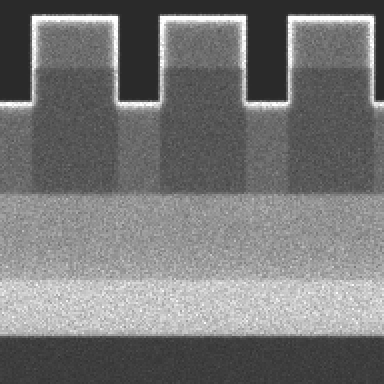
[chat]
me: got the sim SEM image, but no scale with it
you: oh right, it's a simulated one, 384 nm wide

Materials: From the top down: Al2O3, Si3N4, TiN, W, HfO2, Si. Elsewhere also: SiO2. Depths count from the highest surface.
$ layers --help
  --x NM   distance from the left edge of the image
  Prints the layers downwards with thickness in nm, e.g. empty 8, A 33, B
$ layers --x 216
Al2O3 52, Si3N4 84, TiN 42, W 86, HfO2 56, Si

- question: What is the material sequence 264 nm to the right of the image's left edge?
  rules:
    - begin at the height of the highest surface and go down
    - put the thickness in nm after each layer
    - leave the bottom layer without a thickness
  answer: empty 86, SiO2 92, W 86, HfO2 56, Si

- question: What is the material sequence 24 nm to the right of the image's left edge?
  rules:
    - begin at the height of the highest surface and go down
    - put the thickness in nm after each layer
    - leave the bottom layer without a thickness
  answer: empty 86, SiO2 92, W 86, HfO2 56, Si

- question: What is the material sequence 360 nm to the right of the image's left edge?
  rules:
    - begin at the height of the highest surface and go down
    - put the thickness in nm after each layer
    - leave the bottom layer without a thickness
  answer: Al2O3 52, Si3N4 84, TiN 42, W 86, HfO2 56, Si